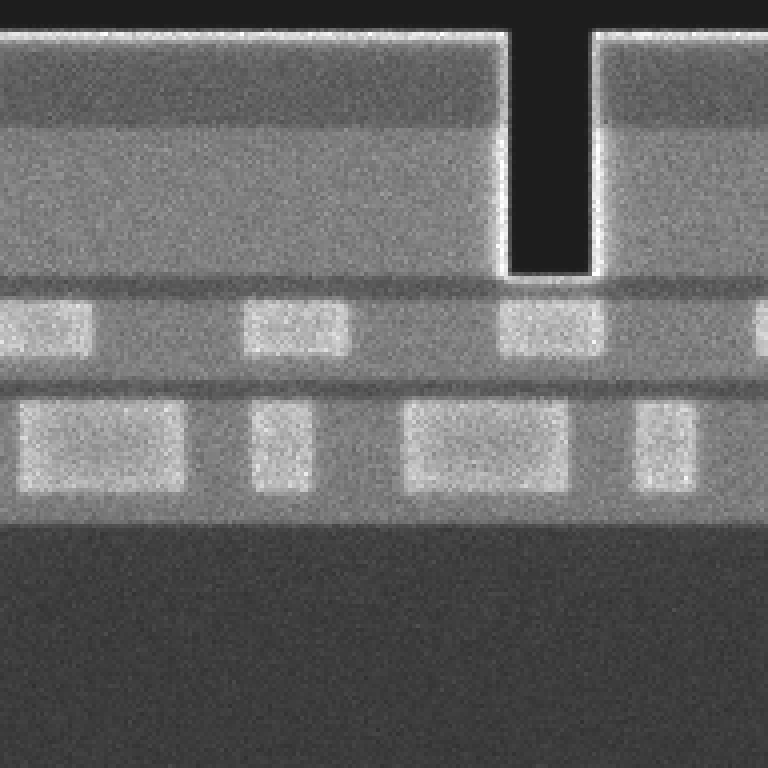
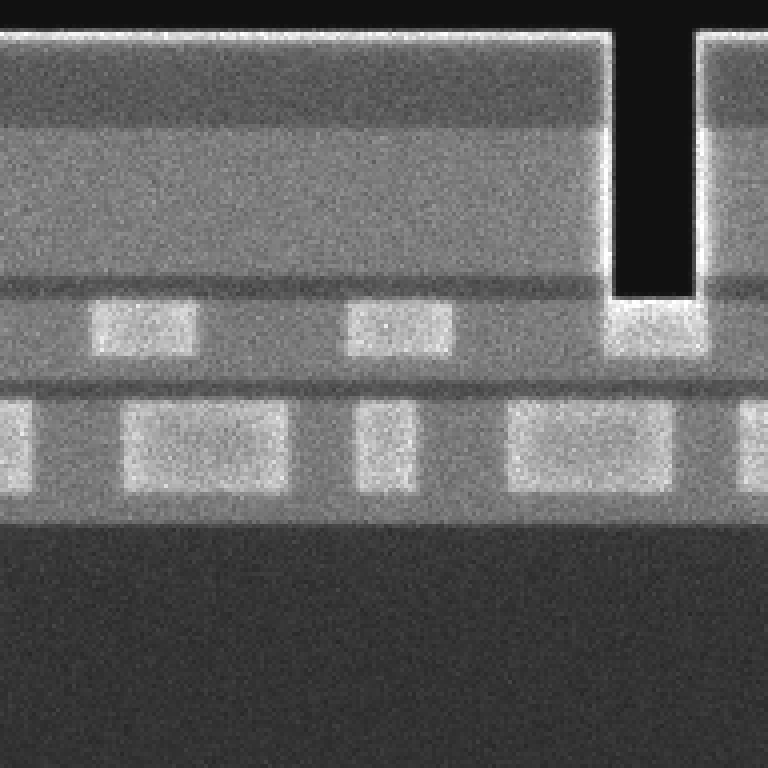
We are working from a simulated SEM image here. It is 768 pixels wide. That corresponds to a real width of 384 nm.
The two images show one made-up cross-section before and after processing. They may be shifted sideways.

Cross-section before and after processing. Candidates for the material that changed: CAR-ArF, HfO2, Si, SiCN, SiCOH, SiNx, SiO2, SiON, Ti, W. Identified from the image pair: SiCN (removed).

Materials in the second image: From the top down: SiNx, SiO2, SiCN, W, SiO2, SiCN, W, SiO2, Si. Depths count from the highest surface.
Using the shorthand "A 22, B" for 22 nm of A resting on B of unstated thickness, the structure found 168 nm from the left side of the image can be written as SiNx 48, SiO2 74, SiCN 12, SiO2 40, SiCN 10, SiO2 62, Si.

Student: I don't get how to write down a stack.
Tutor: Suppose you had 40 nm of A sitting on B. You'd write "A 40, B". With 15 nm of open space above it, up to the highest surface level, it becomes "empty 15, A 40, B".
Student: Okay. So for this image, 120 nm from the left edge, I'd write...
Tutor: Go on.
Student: SiNx 48, SiO2 74, SiCN 12, SiO2 40, SiCN 10, W 46, SiO2 16, Si